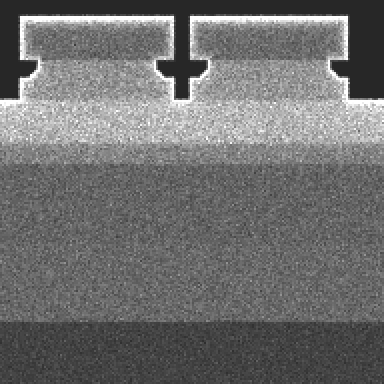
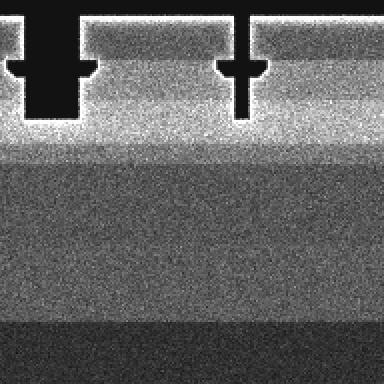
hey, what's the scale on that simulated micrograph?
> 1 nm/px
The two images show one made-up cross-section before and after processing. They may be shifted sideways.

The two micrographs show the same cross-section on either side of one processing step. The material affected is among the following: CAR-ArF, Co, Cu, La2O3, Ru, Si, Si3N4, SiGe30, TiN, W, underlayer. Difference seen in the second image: W removed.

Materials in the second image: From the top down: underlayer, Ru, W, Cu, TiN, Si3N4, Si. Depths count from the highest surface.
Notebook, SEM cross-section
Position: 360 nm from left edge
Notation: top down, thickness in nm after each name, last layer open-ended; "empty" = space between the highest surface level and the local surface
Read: underlayer 44, Ru 40, W 44, Cu 20, TiN 80, Si3N4 78, Si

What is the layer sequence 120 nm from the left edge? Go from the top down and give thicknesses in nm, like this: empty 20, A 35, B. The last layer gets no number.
underlayer 44, Ru 40, W 44, Cu 20, TiN 80, Si3N4 78, Si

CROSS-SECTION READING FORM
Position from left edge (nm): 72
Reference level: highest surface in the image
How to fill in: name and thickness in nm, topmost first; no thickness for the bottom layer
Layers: empty 104, W 24, Cu 20, TiN 80, Si3N4 78, Si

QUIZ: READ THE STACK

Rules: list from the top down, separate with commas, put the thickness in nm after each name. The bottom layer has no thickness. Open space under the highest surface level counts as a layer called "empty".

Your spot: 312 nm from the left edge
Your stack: underlayer 44, Ru 40, W 44, Cu 20, TiN 80, Si3N4 78, Si